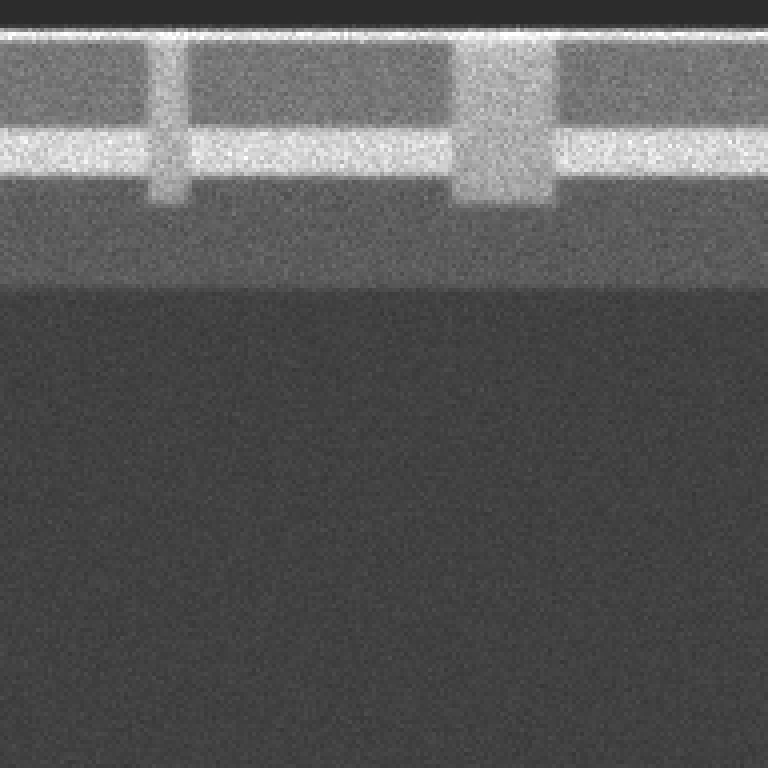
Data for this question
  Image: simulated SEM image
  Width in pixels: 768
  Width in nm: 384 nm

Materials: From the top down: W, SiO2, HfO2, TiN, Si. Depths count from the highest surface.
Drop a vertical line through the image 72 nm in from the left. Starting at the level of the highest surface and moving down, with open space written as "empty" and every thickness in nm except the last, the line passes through W 6, SiO2 42, HfO2 24, TiN 56, Si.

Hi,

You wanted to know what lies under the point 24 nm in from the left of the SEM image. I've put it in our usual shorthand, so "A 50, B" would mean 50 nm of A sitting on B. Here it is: SiO2 48, HfO2 24, TiN 56, Si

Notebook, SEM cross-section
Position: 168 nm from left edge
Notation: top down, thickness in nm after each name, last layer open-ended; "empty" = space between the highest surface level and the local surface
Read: SiO2 48, HfO2 24, TiN 56, Si